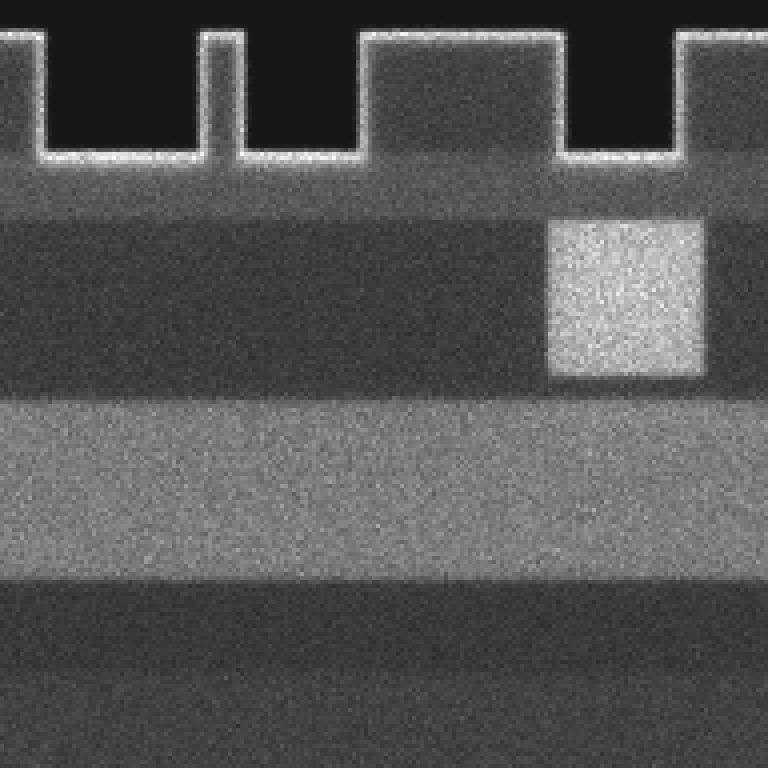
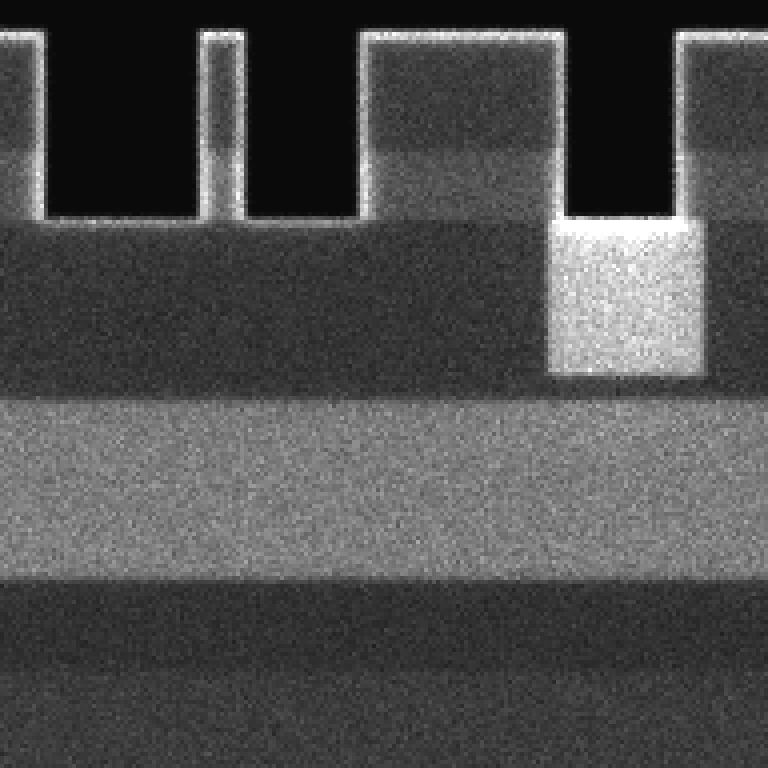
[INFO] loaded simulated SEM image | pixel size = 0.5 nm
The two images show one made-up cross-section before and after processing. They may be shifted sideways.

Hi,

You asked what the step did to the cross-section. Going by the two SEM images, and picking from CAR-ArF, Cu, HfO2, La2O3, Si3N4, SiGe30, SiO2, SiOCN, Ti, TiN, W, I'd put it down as SiO2, removed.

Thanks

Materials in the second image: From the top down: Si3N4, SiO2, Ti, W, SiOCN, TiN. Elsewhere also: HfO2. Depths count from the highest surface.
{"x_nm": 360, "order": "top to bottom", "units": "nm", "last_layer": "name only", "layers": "Si3N4 60, SiO2 34, Ti 90, W 90, SiOCN 46, TiN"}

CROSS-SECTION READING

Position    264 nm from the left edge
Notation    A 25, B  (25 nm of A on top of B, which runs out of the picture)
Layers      Si3N4 60, SiO2 34, Ti 90, W 90, SiOCN 46, TiN